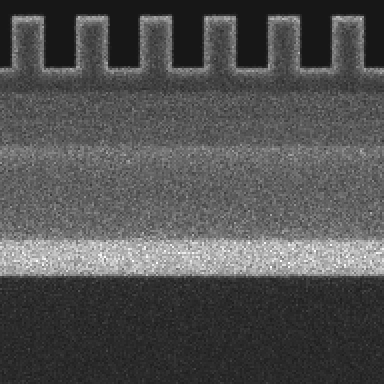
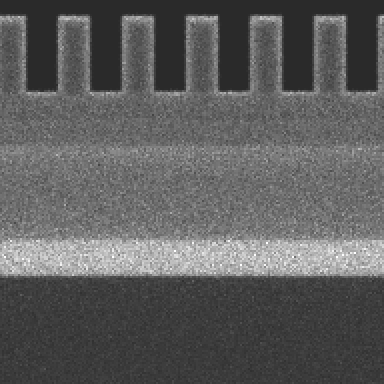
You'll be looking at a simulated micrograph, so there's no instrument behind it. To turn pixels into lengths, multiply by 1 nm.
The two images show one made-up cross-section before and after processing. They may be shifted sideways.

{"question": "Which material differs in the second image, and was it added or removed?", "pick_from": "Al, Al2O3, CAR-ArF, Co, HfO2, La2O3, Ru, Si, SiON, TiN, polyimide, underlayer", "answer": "underlayer, removed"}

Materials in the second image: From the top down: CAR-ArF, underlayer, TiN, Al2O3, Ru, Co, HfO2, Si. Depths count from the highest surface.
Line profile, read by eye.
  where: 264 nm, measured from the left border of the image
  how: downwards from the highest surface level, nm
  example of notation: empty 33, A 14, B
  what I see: CAR-ArF 52, underlayer 24, TiN 28, Al2O3 26, Ru 70, Co 24, HfO2 36, Si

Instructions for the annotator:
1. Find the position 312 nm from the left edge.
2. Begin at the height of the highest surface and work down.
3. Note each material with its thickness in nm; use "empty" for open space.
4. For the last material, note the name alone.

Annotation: empty 76, TiN 28, Al2O3 26, Ru 70, Co 24, HfO2 36, Si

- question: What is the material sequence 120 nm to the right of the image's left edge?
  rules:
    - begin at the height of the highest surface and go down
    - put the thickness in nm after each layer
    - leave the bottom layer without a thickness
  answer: empty 76, TiN 28, Al2O3 26, Ru 70, Co 24, HfO2 36, Si